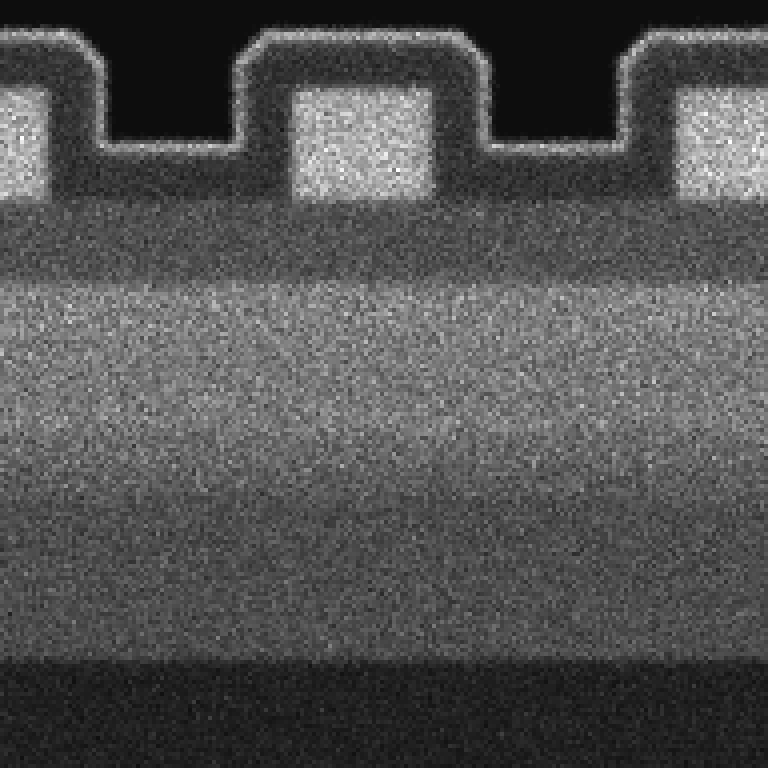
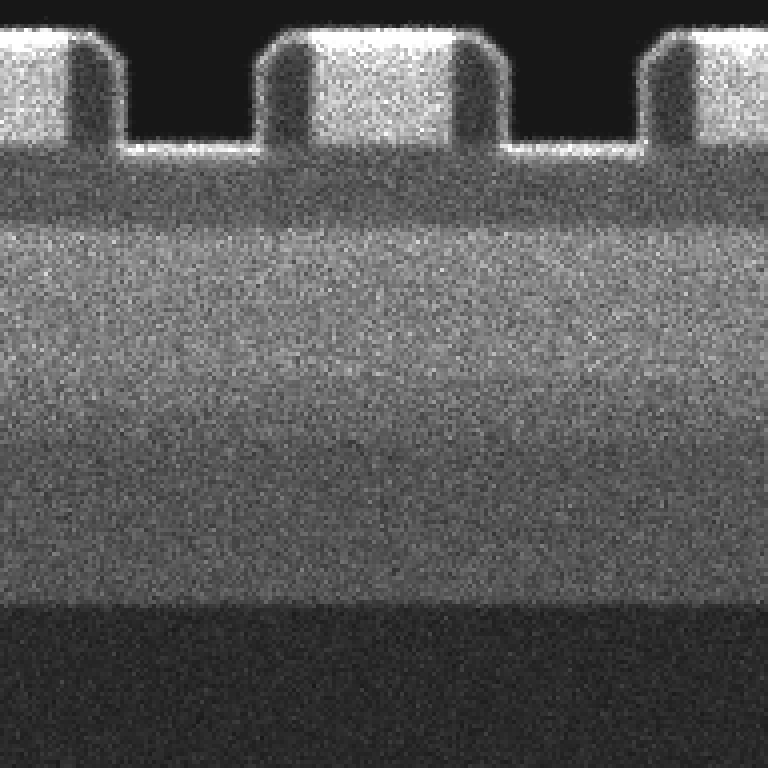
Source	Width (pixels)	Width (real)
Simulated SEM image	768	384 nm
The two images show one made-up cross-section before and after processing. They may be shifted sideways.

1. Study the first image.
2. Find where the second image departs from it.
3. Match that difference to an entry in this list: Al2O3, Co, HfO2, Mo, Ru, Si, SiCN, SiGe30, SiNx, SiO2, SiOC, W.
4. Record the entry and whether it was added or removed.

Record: SiNx / removed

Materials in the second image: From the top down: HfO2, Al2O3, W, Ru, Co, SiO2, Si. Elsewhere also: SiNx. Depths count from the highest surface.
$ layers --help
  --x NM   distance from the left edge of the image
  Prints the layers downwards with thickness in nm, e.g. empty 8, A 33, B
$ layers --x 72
empty 56, Al2O3 42, W 74, Ru 16, Co 16, SiO2 82, Si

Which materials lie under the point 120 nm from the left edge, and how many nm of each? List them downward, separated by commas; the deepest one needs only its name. empty 56, Al2O3 42, W 74, Ru 16, Co 16, SiO2 82, Si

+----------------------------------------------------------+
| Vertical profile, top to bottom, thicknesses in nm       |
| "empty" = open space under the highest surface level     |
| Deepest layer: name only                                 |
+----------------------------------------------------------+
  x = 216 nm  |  HfO2 56, Al2O3 42, W 74, Ru 16, Co 16, SiO2 82, Si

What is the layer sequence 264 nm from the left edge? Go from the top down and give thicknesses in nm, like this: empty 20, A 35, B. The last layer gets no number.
empty 56, Al2O3 42, W 74, Ru 16, Co 16, SiO2 82, Si